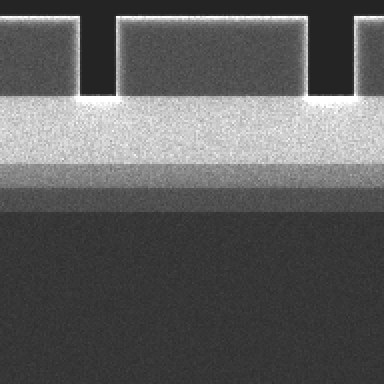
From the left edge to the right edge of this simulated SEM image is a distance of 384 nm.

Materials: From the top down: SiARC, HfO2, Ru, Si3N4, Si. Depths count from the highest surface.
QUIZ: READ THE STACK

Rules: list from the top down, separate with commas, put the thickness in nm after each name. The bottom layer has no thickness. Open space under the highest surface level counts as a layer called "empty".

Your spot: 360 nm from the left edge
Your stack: SiARC 80, HfO2 68, Ru 24, Si3N4 24, Si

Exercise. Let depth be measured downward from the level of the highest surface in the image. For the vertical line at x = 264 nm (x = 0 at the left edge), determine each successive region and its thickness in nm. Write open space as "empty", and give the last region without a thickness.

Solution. SiARC 80, HfO2 68, Ru 24, Si3N4 24, Si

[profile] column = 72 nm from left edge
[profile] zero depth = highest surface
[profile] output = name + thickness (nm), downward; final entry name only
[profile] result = SiARC 80, HfO2 68, Ru 24, Si3N4 24, Si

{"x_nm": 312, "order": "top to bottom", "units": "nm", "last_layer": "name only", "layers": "empty 80, HfO2 68, Ru 24, Si3N4 24, Si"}